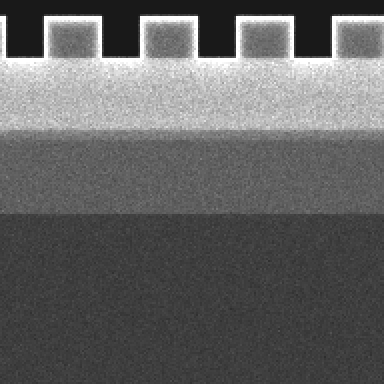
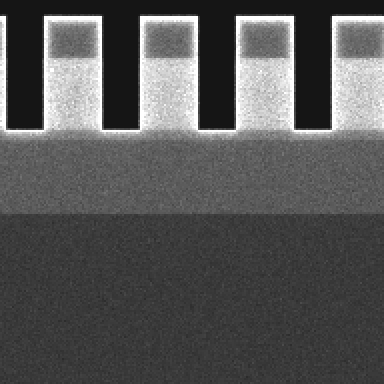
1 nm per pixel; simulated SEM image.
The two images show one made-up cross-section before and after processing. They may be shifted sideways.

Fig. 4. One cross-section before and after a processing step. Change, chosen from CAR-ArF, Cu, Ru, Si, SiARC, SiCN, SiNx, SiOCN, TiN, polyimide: Ru removed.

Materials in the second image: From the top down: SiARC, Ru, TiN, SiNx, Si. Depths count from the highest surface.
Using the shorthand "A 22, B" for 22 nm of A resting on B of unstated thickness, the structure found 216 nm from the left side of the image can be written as empty 114, TiN 10, SiNx 74, Si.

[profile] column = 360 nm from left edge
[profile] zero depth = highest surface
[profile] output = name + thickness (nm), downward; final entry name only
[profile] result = SiARC 42, Ru 72, TiN 10, SiNx 74, Si